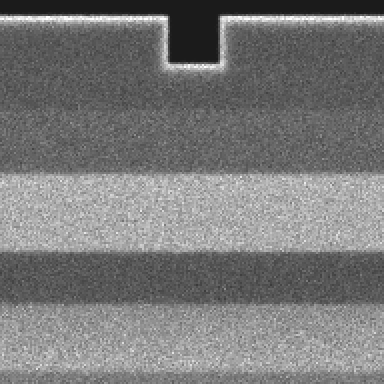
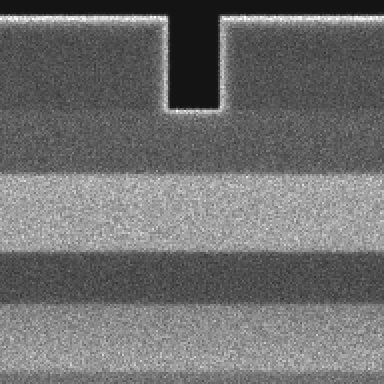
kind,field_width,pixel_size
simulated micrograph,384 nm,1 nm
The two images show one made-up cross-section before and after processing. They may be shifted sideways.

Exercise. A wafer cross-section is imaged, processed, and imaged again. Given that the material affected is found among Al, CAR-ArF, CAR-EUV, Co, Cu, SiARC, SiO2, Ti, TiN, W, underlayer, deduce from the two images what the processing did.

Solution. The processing removed underlayer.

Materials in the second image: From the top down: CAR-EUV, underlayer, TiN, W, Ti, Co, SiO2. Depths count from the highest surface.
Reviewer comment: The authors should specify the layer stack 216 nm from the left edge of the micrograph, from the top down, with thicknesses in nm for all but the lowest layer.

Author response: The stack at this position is empty 94, TiN 64, W 78, Ti 52, Co 68, SiO2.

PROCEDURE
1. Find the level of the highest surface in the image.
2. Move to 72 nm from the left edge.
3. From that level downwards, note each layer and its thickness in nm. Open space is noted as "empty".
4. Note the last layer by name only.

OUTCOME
CAR-EUV 48, underlayer 46, TiN 64, W 78, Ti 52, Co 68, SiO2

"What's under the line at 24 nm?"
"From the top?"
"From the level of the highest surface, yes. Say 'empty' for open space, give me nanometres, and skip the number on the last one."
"CAR-EUV 48, underlayer 46, TiN 64, W 78, Ti 52, Co 68, SiO2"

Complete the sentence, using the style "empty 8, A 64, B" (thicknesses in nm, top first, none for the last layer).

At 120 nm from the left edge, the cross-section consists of CAR-EUV 48, underlayer 46, TiN 64, W 78, Ti 52, Co 68, SiO2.